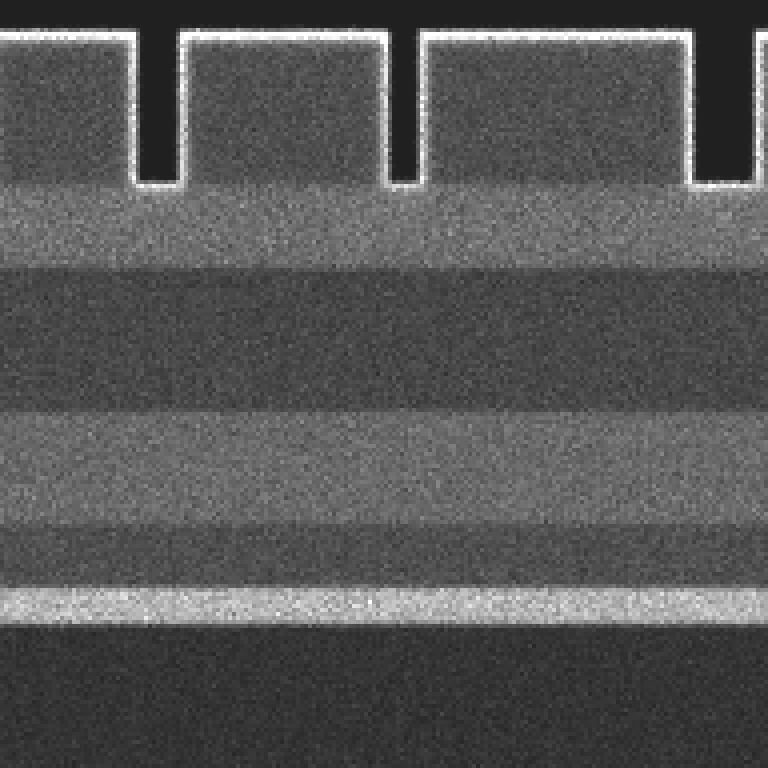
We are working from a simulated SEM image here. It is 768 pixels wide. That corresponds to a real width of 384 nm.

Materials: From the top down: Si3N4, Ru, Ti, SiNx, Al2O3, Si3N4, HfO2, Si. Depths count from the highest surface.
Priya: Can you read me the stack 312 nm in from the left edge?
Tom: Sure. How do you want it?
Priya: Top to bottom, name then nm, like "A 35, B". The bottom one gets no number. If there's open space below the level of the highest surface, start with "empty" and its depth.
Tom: Si3N4 76, Ru 42, Ti 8, SiNx 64, Al2O3 56, Si3N4 32, HfO2 18, Si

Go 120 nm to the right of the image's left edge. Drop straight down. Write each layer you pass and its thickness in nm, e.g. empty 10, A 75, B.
Si3N4 76, Ru 42, Ti 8, SiNx 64, Al2O3 56, Si3N4 32, HfO2 18, Si